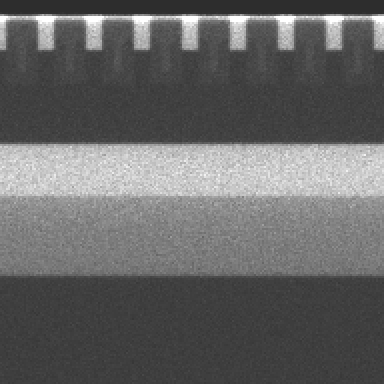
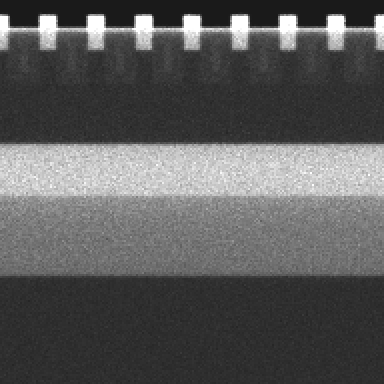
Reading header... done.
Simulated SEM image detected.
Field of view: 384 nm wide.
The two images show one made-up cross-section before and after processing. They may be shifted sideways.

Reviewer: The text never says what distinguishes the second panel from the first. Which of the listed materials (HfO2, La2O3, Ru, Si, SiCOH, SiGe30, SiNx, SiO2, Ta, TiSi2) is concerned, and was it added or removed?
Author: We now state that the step removed SiNx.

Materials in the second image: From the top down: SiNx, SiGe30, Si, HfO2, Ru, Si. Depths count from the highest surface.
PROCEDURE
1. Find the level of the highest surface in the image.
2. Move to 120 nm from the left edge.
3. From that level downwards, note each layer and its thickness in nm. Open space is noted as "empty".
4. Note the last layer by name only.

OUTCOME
empty 12, SiNx 44, SiGe30 12, Si 60, HfO2 52, Ru 80, Si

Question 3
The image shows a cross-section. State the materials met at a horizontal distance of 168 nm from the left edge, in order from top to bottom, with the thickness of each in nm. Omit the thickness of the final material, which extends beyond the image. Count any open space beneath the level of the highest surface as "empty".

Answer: empty 12, SiNx 44, SiGe30 12, Si 60, HfO2 52, Ru 80, Si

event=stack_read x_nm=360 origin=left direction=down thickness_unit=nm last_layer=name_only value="empty 12, SiNx 44, SiGe30 12, Si 60, HfO2 52, Ru 80, Si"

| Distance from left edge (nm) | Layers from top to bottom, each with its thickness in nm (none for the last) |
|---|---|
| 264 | empty 12, SiNx 44, SiGe30 12, Si 60, HfO2 52, Ru 80, Si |